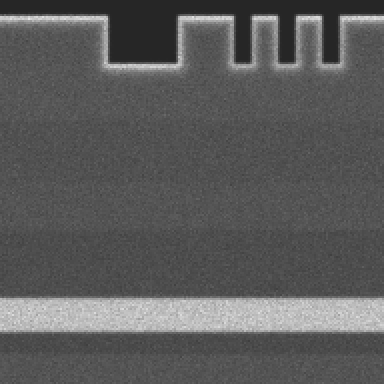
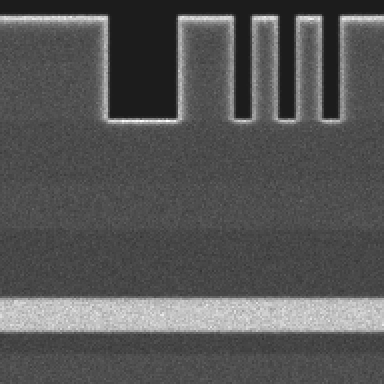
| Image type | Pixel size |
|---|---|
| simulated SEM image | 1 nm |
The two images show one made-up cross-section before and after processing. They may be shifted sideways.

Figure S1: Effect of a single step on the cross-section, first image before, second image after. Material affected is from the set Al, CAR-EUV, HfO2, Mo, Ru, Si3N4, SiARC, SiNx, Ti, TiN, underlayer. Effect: removed underlayer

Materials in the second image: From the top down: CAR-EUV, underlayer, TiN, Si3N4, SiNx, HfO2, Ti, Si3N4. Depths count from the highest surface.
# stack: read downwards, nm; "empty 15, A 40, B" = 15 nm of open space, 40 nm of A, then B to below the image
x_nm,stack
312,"CAR-EUV 48, underlayer 56, TiN 62, Si3N4 48, SiNx 68, HfO2 34, Ti 22, Si3N4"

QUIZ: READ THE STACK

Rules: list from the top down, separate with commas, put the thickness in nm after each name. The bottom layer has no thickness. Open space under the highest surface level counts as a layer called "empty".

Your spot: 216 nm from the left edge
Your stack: CAR-EUV 48, underlayer 56, TiN 62, Si3N4 48, SiNx 68, HfO2 34, Ti 22, Si3N4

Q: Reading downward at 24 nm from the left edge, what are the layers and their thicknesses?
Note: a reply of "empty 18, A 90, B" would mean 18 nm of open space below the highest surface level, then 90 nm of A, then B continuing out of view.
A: CAR-EUV 48, underlayer 56, TiN 62, Si3N4 48, SiNx 68, HfO2 34, Ti 22, Si3N4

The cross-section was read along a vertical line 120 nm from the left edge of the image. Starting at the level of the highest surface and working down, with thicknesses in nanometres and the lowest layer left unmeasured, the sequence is empty 104, TiN 62, Si3N4 48, SiNx 68, HfO2 34, Ti 22, Si3N4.